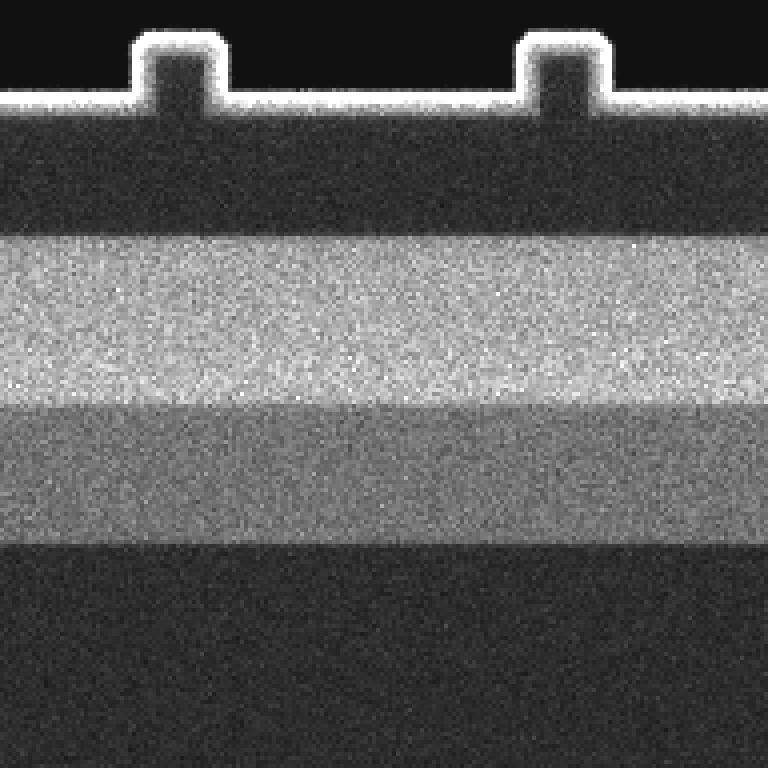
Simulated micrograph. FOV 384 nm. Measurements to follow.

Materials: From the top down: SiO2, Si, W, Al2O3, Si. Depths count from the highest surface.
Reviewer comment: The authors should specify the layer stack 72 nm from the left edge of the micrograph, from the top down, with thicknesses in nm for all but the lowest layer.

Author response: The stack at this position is SiO2 42, Si 60, W 84, Al2O3 70, Si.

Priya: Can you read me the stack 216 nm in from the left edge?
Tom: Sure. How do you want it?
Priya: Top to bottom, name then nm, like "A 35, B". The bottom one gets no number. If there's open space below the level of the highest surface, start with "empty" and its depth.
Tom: empty 30, SiO2 12, Si 60, W 84, Al2O3 70, Si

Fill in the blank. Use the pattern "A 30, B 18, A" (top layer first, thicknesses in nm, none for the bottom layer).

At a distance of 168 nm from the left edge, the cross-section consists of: empty 30, SiO2 12, Si 60, W 84, Al2O3 70, Si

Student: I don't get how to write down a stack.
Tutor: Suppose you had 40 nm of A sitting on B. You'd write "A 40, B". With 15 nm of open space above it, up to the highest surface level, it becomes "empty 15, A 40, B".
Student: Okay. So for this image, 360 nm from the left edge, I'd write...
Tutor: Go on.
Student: empty 30, SiO2 12, Si 60, W 84, Al2O3 70, Si